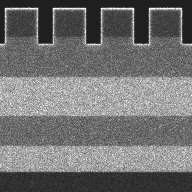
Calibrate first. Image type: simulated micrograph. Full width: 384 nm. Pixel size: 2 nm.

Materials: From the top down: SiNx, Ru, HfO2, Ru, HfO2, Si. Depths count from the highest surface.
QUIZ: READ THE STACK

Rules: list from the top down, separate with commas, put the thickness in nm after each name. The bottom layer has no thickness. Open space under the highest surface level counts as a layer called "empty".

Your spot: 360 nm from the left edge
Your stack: SiNx 58, Ru 80, HfO2 78, Ru 60, HfO2 52, Si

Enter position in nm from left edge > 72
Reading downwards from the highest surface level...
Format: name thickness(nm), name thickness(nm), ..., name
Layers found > SiNx 58, Ru 80, HfO2 78, Ru 60, HfO2 52, Si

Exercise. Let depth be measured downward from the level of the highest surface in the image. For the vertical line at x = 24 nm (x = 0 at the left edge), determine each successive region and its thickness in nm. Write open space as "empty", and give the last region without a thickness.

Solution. SiNx 58, Ru 80, HfO2 78, Ru 60, HfO2 52, Si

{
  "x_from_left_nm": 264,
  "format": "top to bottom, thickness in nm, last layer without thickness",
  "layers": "SiNx 58, Ru 80, HfO2 78, Ru 60, HfO2 52, Si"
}